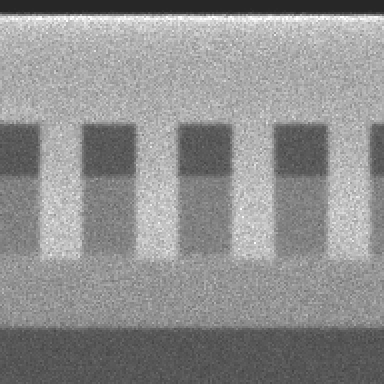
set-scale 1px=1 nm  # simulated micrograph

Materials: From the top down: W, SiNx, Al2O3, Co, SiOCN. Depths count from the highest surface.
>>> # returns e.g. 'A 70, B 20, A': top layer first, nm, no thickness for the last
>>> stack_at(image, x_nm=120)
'W 108, SiNx 52, Al2O3 78, Co 74, SiOCN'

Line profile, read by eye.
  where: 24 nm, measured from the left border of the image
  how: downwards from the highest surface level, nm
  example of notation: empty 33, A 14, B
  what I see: W 108, SiNx 52, Al2O3 78, Co 74, SiOCN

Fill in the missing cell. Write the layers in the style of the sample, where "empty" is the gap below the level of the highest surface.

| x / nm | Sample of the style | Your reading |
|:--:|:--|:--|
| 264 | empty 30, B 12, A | W 244, Co 68, SiOCN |